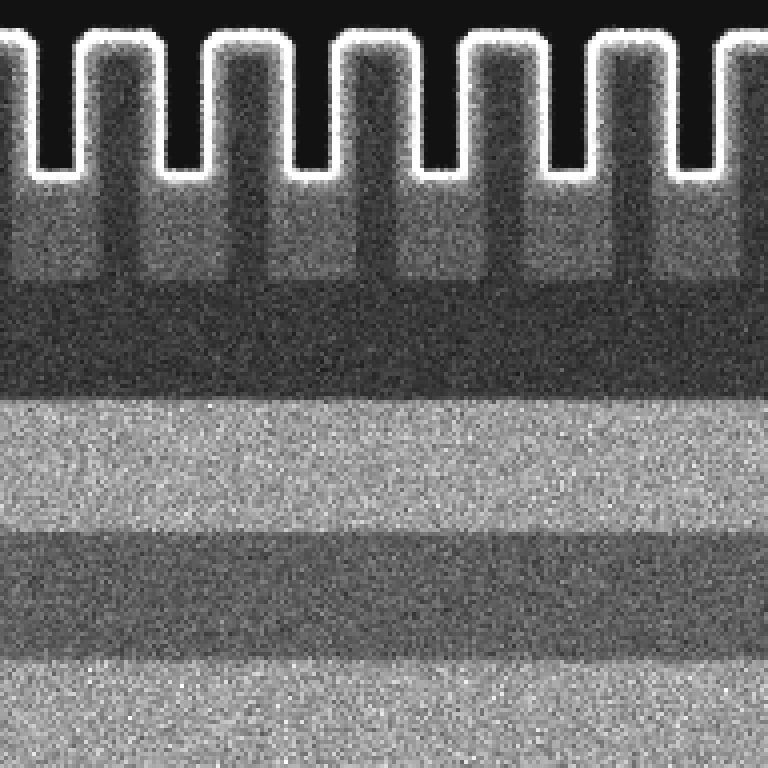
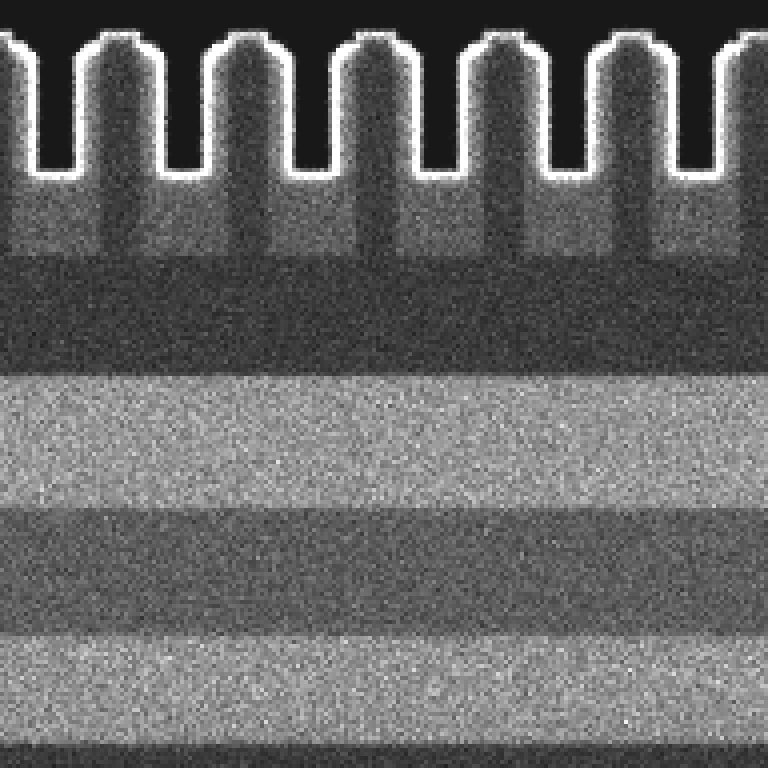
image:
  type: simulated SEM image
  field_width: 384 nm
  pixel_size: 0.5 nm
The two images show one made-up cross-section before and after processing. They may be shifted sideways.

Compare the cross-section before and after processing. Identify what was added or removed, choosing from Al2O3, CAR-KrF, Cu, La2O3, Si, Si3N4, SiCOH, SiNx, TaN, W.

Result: Si3N4 removed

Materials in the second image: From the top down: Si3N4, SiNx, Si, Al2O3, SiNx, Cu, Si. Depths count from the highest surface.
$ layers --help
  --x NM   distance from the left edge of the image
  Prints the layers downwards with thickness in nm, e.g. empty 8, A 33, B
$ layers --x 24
empty 70, SiNx 42, Si 60, Al2O3 66, SiNx 64, Cu 54, Si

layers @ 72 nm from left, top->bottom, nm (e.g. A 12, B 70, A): empty 6, Si3N4 64, SiNx 42, Si 60, Al2O3 66, SiNx 64, Cu 54, Si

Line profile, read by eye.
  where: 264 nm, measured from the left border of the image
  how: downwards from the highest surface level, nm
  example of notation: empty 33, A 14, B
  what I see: empty 6, Si3N4 64, SiNx 42, Si 60, Al2O3 66, SiNx 64, Cu 54, Si